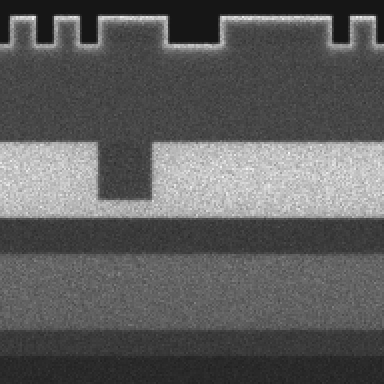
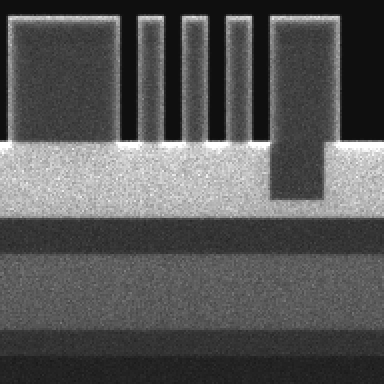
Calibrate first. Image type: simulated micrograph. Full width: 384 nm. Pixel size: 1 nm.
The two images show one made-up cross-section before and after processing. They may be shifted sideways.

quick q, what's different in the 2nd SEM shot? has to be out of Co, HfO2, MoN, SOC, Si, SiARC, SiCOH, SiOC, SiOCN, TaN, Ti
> SOC removed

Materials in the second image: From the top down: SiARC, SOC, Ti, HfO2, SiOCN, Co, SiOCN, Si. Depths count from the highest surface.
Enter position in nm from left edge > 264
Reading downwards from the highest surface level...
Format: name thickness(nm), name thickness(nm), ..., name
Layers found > empty 126, HfO2 76, SiOCN 36, Co 76, SiOCN 26, Si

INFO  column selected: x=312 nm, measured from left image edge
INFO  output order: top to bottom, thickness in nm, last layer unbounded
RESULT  SiARC 28, SOC 98, Ti 58, HfO2 18, SiOCN 36, Co 76, SiOCN 26, Si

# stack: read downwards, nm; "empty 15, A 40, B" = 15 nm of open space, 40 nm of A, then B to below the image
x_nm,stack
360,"empty 126, HfO2 76, SiOCN 36, Co 76, SiOCN 26, Si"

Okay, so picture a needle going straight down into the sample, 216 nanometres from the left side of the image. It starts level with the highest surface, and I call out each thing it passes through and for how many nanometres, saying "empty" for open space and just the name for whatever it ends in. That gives empty 126, HfO2 76, SiOCN 36, Co 76, SiOCN 26, Si